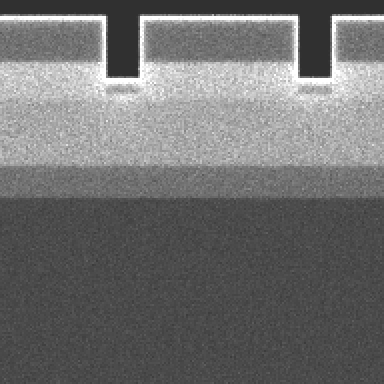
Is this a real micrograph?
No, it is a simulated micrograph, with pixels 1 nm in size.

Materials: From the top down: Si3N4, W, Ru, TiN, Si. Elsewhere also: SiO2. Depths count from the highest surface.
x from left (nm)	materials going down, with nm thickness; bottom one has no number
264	Si3N4 46, W 38, Ru 66, TiN 32, Si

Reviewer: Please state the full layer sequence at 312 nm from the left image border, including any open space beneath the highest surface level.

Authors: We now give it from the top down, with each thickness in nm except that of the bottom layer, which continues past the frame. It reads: empty 62, SiO2 16, W 6, Ru 66, TiN 32, Si